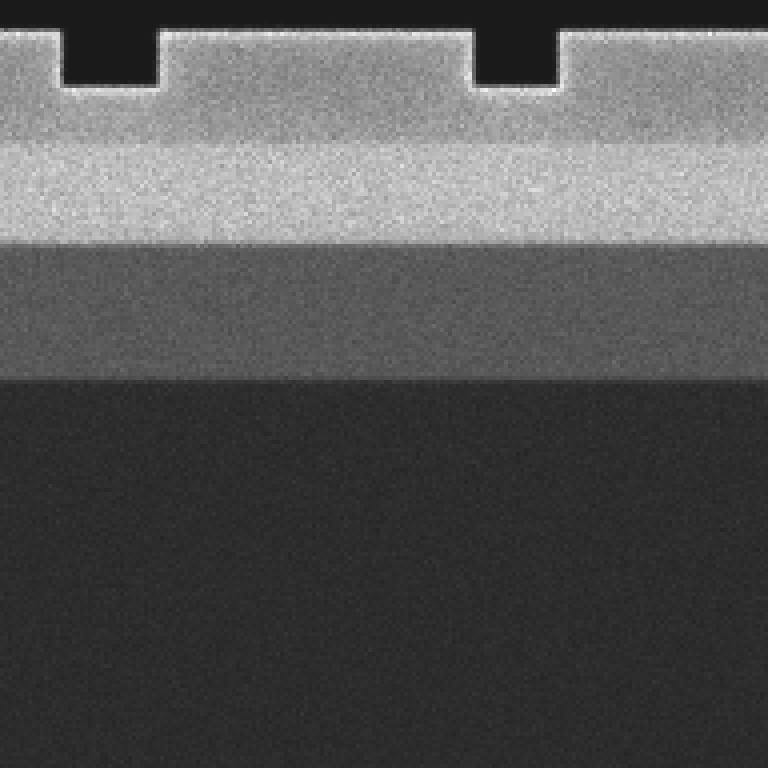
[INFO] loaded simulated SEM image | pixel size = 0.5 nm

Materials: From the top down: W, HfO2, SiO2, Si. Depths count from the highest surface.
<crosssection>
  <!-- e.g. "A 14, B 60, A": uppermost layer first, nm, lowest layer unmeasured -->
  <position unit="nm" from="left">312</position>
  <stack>W 56, HfO2 50, SiO2 68, Si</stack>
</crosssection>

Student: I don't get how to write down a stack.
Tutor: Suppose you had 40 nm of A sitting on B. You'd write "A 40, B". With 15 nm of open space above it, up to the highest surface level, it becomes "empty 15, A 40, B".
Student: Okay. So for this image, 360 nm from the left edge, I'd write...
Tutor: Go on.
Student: W 56, HfO2 50, SiO2 68, Si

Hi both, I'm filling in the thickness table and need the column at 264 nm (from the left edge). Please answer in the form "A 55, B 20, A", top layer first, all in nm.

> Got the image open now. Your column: empty 28, W 28, HfO2 50, SiO2 68, Si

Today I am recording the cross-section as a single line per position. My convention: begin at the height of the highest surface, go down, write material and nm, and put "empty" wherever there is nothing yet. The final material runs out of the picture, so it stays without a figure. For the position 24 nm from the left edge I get W 56, HfO2 50, SiO2 68, Si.